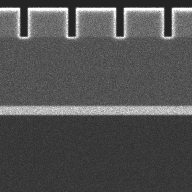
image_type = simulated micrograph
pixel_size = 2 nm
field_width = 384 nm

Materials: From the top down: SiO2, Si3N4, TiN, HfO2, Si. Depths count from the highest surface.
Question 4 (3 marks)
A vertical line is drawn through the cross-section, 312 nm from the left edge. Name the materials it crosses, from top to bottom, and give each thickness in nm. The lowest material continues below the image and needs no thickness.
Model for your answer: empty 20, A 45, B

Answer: SiO2 58, Si3N4 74, TiN 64, HfO2 18, Si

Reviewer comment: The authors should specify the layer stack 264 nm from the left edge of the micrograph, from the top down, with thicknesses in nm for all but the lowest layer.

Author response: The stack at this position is SiO2 58, Si3N4 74, TiN 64, HfO2 18, Si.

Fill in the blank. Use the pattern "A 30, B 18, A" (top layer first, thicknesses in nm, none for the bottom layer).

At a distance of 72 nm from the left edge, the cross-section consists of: SiO2 58, Si3N4 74, TiN 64, HfO2 18, Si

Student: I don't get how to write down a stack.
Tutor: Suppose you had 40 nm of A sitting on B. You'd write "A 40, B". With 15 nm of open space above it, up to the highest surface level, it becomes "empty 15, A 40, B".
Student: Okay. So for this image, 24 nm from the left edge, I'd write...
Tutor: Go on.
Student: SiO2 58, Si3N4 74, TiN 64, HfO2 18, Si